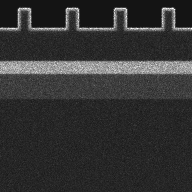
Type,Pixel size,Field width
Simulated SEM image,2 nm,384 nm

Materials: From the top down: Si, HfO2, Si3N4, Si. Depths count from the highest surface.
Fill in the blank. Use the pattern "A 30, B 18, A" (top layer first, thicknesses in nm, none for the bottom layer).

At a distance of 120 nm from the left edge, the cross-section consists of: empty 40, Si 66, HfO2 26, Si3N4 50, Si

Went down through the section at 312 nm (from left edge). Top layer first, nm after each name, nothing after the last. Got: empty 40, Si 66, HfO2 26, Si3N4 50, Si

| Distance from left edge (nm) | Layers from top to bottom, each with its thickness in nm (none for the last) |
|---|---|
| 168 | empty 40, Si 66, HfO2 26, Si3N4 50, Si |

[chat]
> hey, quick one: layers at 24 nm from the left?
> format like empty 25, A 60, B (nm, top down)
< empty 40, Si 66, HfO2 26, Si3N4 50, Si